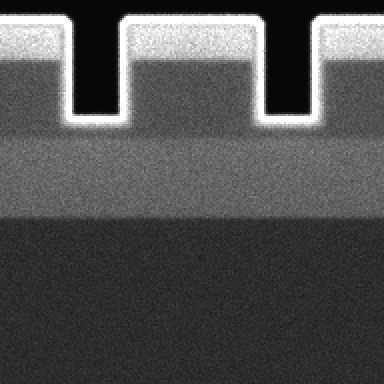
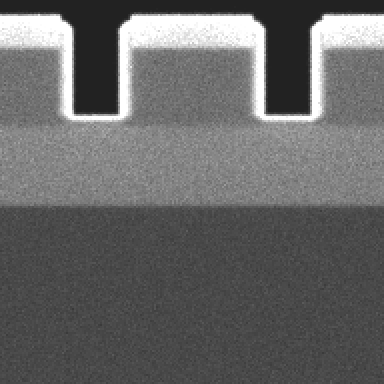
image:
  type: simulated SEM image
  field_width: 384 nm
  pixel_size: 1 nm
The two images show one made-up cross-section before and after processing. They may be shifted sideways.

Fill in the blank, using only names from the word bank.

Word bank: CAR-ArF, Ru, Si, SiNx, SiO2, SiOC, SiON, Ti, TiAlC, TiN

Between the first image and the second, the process removed SiO2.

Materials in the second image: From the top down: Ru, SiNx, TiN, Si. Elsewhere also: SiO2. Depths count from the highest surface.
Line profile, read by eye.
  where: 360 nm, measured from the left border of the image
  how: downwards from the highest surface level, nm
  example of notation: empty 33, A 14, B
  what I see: Ru 32, SiNx 78, TiN 80, Si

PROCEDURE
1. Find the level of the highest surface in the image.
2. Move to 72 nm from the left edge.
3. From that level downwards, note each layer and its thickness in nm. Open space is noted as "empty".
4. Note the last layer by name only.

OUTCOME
empty 100, SiNx 10, TiN 80, Si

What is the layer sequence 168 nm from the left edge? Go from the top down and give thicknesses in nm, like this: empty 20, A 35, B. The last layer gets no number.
Ru 32, SiNx 78, TiN 80, Si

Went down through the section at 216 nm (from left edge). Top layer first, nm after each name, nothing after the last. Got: Ru 32, SiNx 78, TiN 80, Si